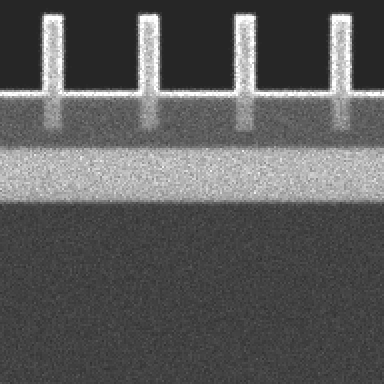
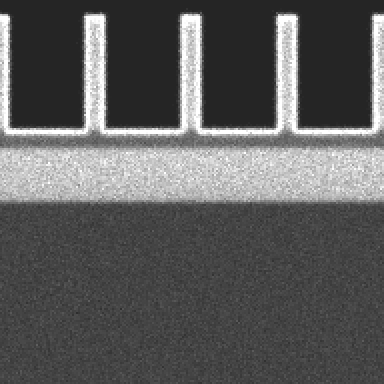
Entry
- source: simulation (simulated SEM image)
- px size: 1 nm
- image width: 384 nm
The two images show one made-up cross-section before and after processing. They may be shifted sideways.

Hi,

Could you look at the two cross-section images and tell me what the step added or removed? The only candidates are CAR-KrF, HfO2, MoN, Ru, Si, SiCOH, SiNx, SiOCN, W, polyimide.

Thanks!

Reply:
removed SiNx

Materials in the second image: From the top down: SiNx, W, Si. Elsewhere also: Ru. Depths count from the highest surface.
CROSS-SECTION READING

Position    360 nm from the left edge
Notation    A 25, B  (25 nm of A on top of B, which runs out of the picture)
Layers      empty 114, SiNx 18, W 54, Si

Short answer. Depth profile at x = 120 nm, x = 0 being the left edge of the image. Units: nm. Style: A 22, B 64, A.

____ empty 114, SiNx 18, W 54, Si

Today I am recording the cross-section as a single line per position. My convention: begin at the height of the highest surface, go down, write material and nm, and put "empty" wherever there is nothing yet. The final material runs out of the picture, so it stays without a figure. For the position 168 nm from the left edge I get empty 114, SiNx 18, W 54, Si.